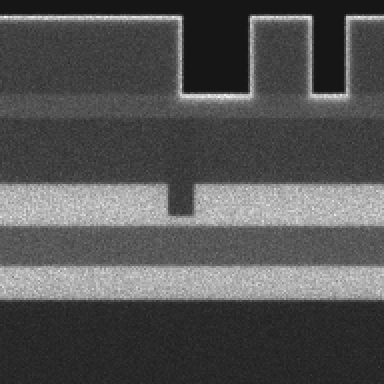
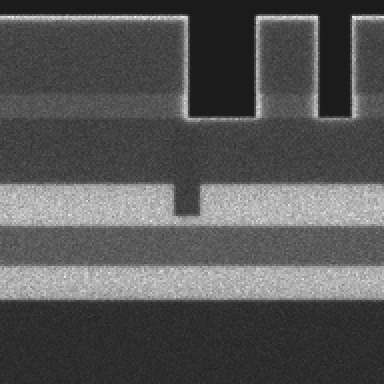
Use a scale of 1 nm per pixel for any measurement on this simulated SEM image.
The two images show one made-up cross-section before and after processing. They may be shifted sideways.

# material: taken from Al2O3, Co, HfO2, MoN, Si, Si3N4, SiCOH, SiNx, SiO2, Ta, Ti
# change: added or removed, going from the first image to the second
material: SiO2
change: removed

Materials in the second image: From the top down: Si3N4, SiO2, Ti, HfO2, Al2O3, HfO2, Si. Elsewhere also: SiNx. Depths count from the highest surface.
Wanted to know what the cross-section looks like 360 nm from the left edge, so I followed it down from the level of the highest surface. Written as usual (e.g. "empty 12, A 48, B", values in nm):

Si3N4 78, SiO2 24, Ti 66, HfO2 42, Al2O3 40, HfO2 34, Si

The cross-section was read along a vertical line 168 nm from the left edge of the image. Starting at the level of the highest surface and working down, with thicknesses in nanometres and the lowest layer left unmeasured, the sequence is Si3N4 78, SiO2 24, Ti 66, HfO2 42, Al2O3 40, HfO2 34, Si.